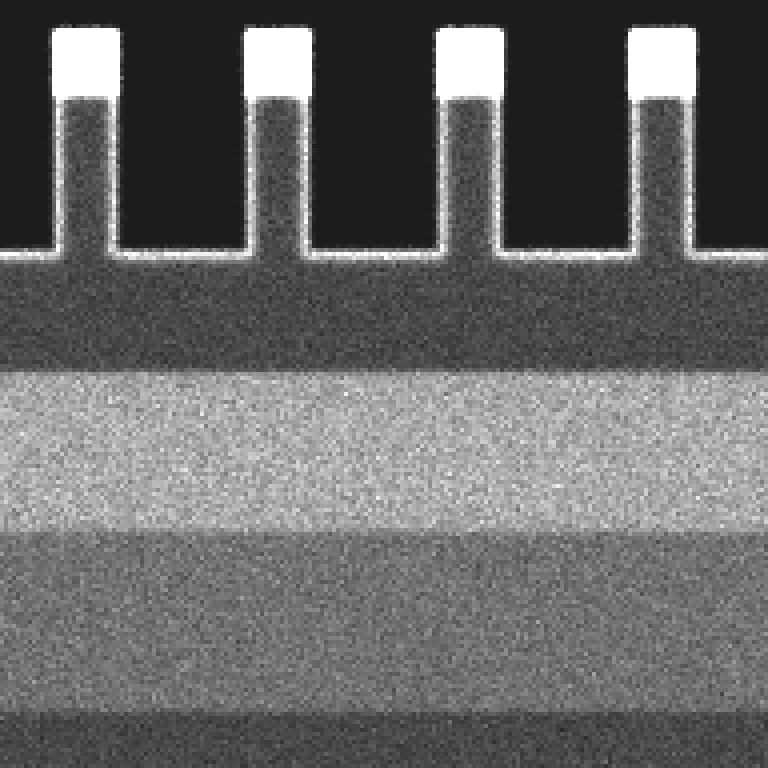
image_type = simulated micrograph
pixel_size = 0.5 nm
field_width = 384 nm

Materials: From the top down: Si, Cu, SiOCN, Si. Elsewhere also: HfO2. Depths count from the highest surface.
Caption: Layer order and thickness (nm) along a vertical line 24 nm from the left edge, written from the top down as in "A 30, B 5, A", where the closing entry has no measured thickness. empty 110, Si 60, Cu 80, SiOCN 90, Si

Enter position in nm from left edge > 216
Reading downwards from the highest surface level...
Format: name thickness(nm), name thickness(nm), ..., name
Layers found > empty 110, Si 60, Cu 80, SiOCN 90, Si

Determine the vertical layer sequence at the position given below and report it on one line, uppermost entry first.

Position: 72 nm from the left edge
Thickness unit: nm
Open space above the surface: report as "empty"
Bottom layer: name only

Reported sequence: empty 110, Si 60, Cu 80, SiOCN 90, Si